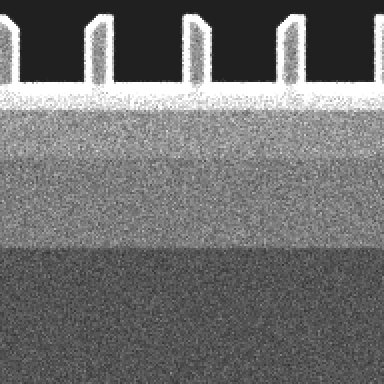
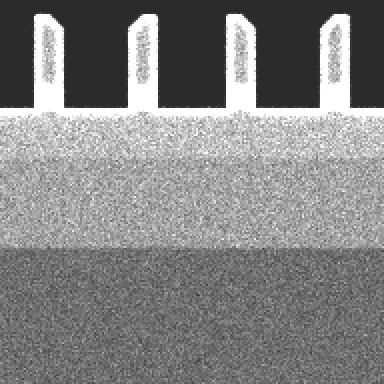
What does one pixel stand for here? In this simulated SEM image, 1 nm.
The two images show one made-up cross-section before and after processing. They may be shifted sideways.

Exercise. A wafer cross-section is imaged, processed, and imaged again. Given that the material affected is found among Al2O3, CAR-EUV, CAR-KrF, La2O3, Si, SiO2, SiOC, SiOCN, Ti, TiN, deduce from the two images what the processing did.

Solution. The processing removed Al2O3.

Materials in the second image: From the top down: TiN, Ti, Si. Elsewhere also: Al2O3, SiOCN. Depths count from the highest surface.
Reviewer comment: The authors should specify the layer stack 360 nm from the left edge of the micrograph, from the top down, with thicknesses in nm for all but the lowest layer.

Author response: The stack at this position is empty 94, TiN 48, Ti 90, Si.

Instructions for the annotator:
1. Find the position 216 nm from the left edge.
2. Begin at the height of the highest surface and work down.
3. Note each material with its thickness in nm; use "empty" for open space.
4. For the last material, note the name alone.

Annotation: empty 94, TiN 48, Ti 90, Si